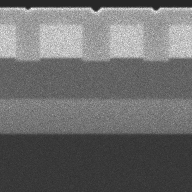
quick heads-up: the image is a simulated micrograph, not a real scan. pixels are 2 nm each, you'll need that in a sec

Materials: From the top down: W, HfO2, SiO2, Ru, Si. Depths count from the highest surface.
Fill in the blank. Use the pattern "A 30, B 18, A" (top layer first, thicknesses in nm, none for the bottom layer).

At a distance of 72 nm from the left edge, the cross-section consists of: W 106, SiO2 76, Ru 70, Si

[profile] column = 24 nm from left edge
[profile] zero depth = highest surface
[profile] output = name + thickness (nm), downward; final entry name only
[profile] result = W 34, HfO2 66, SiO2 82, Ru 70, Si